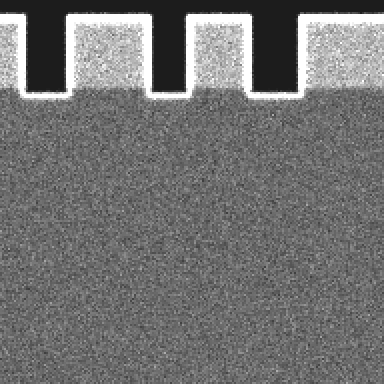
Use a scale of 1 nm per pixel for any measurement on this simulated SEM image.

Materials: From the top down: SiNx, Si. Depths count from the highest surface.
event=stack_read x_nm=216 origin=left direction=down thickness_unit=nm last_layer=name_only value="SiNx 72, Si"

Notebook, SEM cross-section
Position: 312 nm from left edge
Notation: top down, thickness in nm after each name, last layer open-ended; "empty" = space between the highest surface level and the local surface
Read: SiNx 72, Si